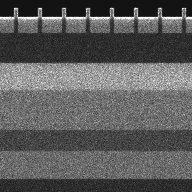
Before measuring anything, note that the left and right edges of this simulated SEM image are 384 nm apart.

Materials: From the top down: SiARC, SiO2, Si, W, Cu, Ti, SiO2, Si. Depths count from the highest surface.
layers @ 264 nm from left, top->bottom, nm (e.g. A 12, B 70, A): empty 18, SiARC 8, SiO2 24, Si 60, W 54, Cu 80, Ti 42, SiO2 56, Si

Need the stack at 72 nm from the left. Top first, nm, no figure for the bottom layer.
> empty 18, SiARC 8, SiO2 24, Si 60, W 54, Cu 80, Ti 42, SiO2 56, Si